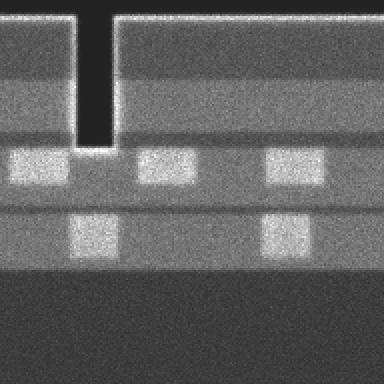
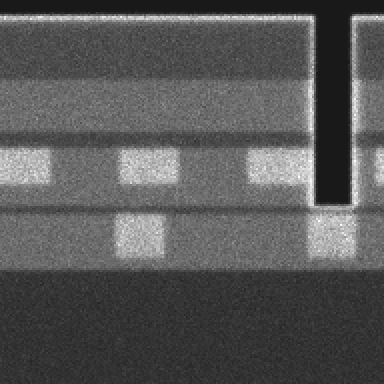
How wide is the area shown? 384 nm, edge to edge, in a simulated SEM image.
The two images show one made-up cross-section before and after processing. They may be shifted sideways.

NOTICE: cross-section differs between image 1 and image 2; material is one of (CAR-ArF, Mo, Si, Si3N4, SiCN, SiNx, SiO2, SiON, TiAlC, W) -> removed: SiO2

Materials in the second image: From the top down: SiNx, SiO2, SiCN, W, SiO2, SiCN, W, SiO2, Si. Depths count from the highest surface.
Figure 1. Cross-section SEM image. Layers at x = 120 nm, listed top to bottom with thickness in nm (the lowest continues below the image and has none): SiNx 64, SiO2 52, SiCN 16, W 36, SiO2 22, SiCN 8, W 44, SiO2 12, Si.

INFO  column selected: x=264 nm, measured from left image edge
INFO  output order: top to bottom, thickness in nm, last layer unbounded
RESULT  SiNx 64, SiO2 52, SiCN 16, W 36, SiO2 22, SiCN 8, SiO2 56, Si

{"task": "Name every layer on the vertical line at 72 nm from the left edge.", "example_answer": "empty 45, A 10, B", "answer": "SiNx 64, SiO2 52, SiCN 16, SiO2 58, SiCN 8, SiO2 56, Si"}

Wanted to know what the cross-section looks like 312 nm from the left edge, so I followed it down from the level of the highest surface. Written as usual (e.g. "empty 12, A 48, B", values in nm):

SiNx 64, SiO2 52, SiCN 16, SiO2 58, SiCN 8, W 44, SiO2 12, Si